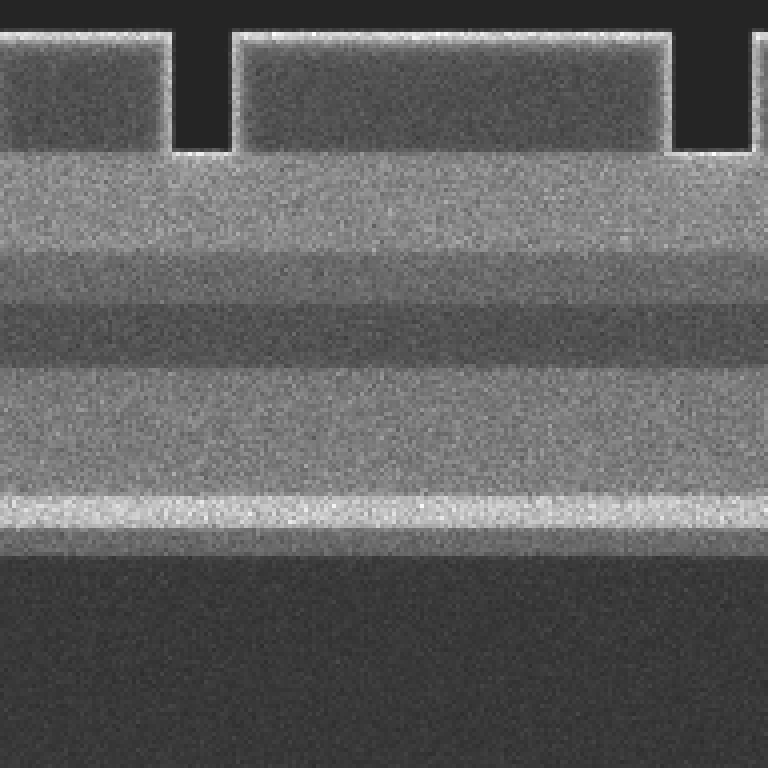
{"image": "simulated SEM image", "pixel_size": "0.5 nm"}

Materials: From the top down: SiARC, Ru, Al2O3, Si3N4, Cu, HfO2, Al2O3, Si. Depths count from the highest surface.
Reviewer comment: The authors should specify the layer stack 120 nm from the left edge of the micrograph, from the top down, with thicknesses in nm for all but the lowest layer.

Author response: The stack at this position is SiARC 60, Ru 50, Al2O3 26, Si3N4 32, Cu 64, HfO2 16, Al2O3 14, Si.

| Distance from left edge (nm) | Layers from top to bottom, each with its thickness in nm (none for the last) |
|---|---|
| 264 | SiARC 60, Ru 50, Al2O3 26, Si3N4 32, Cu 64, HfO2 16, Al2O3 14, Si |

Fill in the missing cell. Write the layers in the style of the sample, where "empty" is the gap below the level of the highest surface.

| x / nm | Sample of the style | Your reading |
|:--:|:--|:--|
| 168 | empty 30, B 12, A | SiARC 60, Ru 50, Al2O3 26, Si3N4 32, Cu 64, HfO2 16, Al2O3 14, Si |